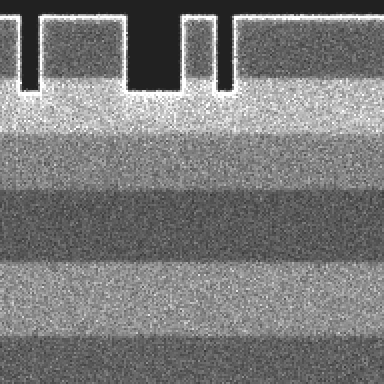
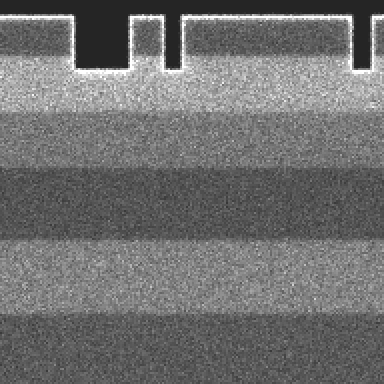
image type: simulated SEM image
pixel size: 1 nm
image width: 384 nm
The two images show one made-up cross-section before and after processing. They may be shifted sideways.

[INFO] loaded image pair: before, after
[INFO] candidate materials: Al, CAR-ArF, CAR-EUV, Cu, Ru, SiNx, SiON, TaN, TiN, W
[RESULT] removed TiN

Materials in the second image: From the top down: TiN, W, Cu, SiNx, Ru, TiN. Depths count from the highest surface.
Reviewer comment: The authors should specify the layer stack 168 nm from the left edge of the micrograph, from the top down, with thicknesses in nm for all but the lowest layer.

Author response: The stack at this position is empty 54, W 42, Cu 56, SiNx 72, Ru 74, TiN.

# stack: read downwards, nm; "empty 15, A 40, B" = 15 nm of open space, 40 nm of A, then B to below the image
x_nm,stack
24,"TiN 40, W 56, Cu 56, SiNx 72, Ru 74, TiN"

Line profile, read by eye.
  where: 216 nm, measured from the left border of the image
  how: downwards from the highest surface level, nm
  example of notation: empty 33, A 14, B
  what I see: TiN 40, W 56, Cu 56, SiNx 72, Ru 74, TiN